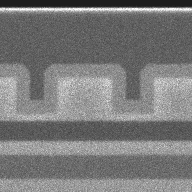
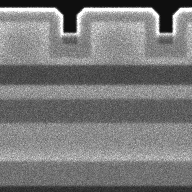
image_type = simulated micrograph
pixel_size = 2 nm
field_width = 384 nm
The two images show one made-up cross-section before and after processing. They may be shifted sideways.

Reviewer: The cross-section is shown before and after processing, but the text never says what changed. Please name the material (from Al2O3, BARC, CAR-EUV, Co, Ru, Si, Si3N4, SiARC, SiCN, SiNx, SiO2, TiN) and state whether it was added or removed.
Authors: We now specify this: SiARC, removed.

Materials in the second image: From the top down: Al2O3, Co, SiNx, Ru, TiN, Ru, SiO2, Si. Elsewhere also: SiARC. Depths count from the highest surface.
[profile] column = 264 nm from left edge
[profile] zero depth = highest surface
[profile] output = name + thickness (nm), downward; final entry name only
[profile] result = Al2O3 28, Co 86, SiNx 40, Ru 28, TiN 48, Ru 76, SiO2 50, Si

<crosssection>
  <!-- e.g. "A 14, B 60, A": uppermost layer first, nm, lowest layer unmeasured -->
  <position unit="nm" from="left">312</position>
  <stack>empty 10, Al2O3 90, Co 14, SiNx 40, Ru 28, TiN 48, Ru 76, SiO2 50, Si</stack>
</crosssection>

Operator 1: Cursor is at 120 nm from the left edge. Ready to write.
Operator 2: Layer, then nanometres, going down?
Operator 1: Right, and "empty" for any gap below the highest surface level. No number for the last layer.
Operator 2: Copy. empty 10, Al2O3 90, Co 14, SiNx 40, Ru 28, TiN 48, Ru 76, SiO2 50, Si